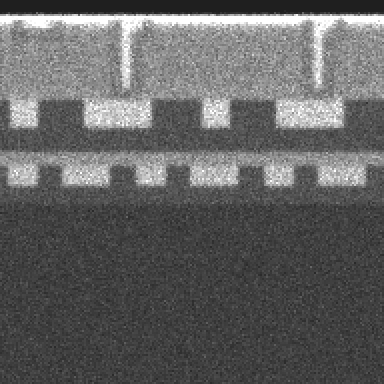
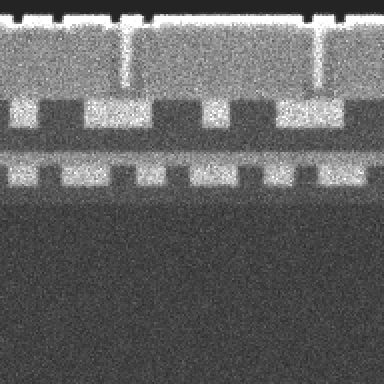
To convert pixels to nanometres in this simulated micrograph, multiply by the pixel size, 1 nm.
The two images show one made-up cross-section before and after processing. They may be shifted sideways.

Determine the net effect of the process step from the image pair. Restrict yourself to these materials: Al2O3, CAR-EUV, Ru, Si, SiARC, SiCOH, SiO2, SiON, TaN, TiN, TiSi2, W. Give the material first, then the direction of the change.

TiN: removed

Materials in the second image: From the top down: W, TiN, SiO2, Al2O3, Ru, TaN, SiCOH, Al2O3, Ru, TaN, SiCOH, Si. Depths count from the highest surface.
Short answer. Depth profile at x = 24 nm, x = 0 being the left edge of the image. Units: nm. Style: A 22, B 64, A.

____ W 12, TiN 12, SiO2 46, Al2O3 14, Ru 18, TaN 10, SiCOH 24, Al2O3 14, Ru 10, TaN 10, SiCOH 18, Si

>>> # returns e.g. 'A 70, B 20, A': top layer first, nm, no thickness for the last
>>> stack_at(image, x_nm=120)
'empty 8, TiN 76, Ru 18, TaN 10, SiCOH 24, Al2O3 14, SiCOH 38, Si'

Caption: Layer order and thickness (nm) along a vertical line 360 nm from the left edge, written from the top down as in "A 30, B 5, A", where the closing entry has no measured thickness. SiO2 70, Al2O3 14, SiCOH 52, Al2O3 14, TaN 20, SiCOH 18, Si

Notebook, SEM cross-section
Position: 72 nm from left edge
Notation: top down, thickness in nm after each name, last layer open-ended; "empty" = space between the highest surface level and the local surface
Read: SiO2 70, Al2O3 14, SiCOH 52, Al2O3 14, Ru 10, TaN 10, SiCOH 18, Si